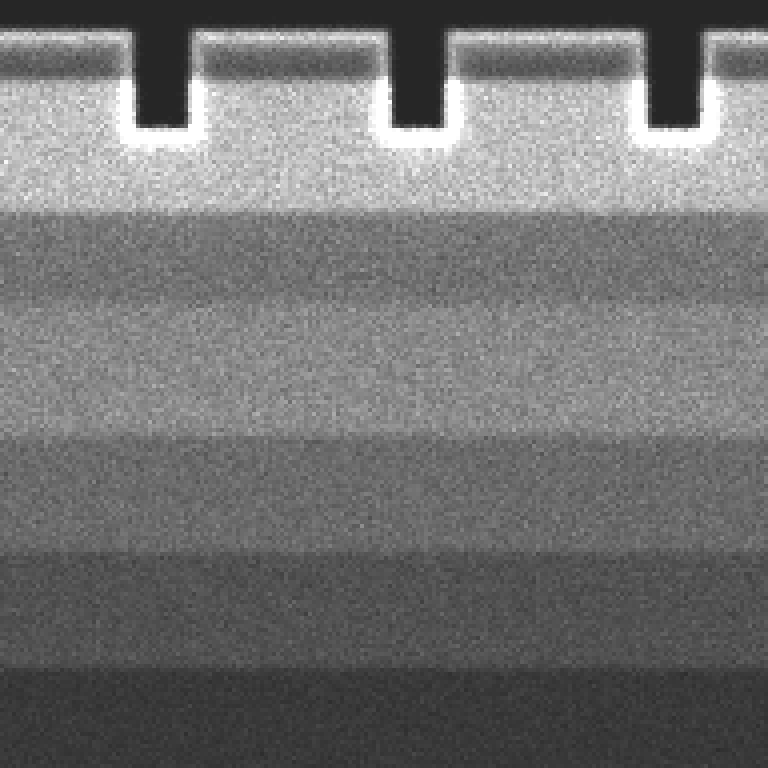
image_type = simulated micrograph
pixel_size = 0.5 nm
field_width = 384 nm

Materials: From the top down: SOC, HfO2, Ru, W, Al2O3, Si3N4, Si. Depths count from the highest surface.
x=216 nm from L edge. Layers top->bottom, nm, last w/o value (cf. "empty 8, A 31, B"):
empty 50, HfO2 40, Ru 46, W 66, Al2O3 58, Si3N4 58, Si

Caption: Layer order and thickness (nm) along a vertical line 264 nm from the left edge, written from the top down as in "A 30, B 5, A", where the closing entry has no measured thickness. SOC 24, HfO2 66, Ru 46, W 66, Al2O3 58, Si3N4 58, Si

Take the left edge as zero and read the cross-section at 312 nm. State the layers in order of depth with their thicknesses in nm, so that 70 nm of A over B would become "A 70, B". SOC 24, HfO2 66, Ru 46, W 66, Al2O3 58, Si3N4 58, Si